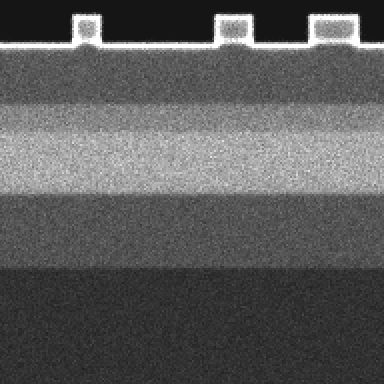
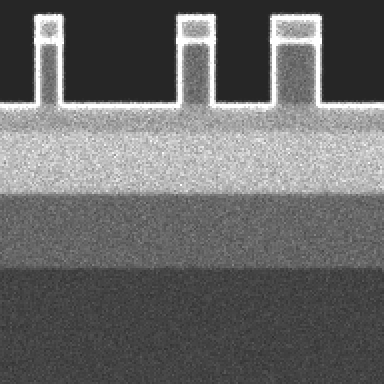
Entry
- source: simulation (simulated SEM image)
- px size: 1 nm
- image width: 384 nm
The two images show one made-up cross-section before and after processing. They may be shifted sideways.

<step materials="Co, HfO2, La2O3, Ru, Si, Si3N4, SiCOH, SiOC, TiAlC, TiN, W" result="removed Si3N4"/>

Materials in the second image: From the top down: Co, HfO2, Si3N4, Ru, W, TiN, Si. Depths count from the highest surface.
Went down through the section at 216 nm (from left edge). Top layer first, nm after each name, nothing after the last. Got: empty 88, Ru 28, W 62, TiN 74, Si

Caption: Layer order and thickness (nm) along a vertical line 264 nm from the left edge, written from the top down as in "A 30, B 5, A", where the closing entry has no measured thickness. empty 88, Ru 28, W 62, TiN 74, Si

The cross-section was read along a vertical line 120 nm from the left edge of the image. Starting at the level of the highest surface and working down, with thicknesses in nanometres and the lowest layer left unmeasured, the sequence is empty 88, Ru 28, W 62, TiN 74, Si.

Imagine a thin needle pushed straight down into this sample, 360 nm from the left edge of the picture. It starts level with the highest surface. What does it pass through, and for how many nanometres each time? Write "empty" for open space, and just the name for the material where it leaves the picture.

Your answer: empty 88, Ru 28, W 62, TiN 74, Si